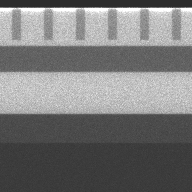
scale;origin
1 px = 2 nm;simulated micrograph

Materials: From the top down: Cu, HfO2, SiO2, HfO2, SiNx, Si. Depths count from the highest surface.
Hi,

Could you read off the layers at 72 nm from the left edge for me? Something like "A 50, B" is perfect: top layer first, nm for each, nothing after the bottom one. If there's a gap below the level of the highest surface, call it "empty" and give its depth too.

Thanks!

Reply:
HfO2 76, SiO2 52, HfO2 84, SiNx 58, Si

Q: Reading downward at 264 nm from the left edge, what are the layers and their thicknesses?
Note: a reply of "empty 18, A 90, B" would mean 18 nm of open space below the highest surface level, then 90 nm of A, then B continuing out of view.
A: HfO2 76, SiO2 52, HfO2 84, SiNx 58, Si